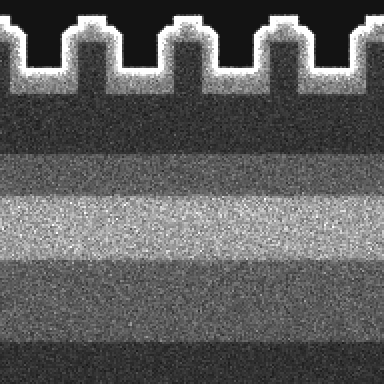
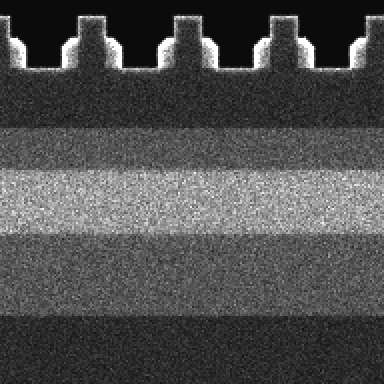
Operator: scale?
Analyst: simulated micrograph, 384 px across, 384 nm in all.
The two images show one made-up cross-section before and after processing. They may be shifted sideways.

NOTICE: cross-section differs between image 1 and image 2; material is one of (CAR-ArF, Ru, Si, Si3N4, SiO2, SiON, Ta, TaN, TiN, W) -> removed: SiO2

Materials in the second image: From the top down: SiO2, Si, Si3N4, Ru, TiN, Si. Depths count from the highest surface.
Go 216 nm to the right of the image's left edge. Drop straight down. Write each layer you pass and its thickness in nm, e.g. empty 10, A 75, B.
empty 30, SiO2 22, Si 60, Si3N4 42, Ru 64, TiN 82, Si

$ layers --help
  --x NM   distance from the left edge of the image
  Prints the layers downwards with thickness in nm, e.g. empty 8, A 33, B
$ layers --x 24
empty 30, SiO2 22, Si 60, Si3N4 42, Ru 64, TiN 82, Si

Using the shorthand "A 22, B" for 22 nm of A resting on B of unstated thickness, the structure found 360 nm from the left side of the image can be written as empty 22, SiO2 30, Si 60, Si3N4 42, Ru 64, TiN 82, Si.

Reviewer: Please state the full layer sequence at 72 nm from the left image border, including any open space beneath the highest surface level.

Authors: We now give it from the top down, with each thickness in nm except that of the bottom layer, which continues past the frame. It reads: empty 22, SiO2 30, Si 60, Si3N4 42, Ru 64, TiN 82, Si